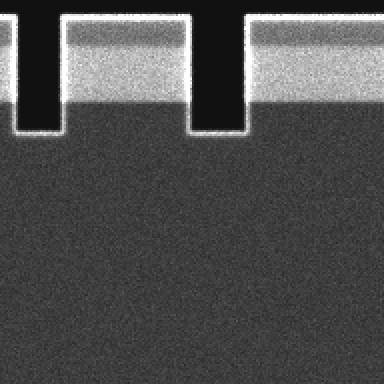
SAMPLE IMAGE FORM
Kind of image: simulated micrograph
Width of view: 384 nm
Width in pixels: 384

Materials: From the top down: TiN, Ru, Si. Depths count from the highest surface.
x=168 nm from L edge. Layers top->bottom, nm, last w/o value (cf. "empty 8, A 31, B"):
TiN 30, Ru 56, Si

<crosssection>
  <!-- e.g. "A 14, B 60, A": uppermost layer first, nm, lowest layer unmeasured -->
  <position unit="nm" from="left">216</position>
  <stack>empty 116, Si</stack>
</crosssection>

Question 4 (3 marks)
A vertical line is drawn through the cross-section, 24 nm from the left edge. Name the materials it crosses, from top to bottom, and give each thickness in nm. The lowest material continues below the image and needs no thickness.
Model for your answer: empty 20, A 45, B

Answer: empty 116, Si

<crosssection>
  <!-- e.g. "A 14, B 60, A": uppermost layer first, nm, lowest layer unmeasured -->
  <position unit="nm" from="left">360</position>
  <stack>TiN 30, Ru 56, Si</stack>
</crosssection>